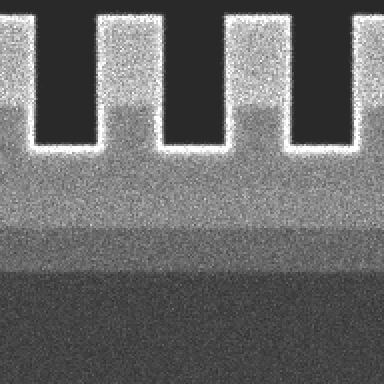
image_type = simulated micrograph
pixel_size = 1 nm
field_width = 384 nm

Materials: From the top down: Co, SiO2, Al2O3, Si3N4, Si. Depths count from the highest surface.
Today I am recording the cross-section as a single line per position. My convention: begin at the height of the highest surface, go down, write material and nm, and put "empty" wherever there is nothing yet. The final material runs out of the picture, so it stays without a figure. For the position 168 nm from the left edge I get empty 130, SiO2 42, Al2O3 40, Si3N4 44, Si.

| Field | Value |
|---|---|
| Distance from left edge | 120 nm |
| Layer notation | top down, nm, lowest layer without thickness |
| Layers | Co 90, SiO2 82, Al2O3 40, Si3N4 44, Si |